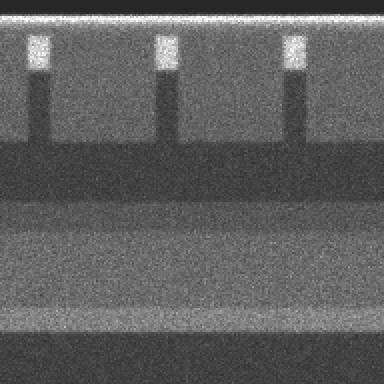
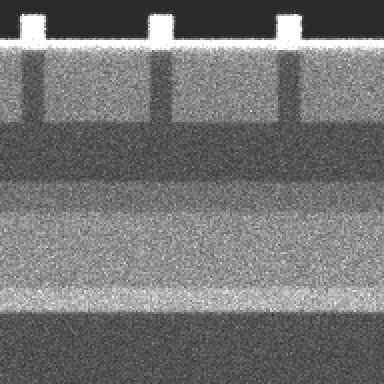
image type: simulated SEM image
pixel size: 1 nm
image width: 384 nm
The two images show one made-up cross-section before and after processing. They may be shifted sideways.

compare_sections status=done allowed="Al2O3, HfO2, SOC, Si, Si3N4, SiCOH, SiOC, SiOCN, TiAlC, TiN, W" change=removed material="SOC"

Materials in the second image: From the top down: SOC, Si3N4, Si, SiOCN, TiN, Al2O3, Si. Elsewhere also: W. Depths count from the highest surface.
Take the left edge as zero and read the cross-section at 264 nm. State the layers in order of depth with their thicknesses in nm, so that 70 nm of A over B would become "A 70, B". empty 24, SOC 38, Si3N4 44, Si 60, SiOCN 30, TiN 76, Al2O3 24, Si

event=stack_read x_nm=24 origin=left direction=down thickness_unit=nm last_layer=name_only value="W 34, Si 132, SiOCN 30, TiN 76, Al2O3 24, Si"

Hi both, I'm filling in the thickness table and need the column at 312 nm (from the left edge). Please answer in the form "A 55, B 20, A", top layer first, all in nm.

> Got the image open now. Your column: empty 24, SOC 38, Si3N4 44, Si 60, SiOCN 30, TiN 76, Al2O3 24, Si